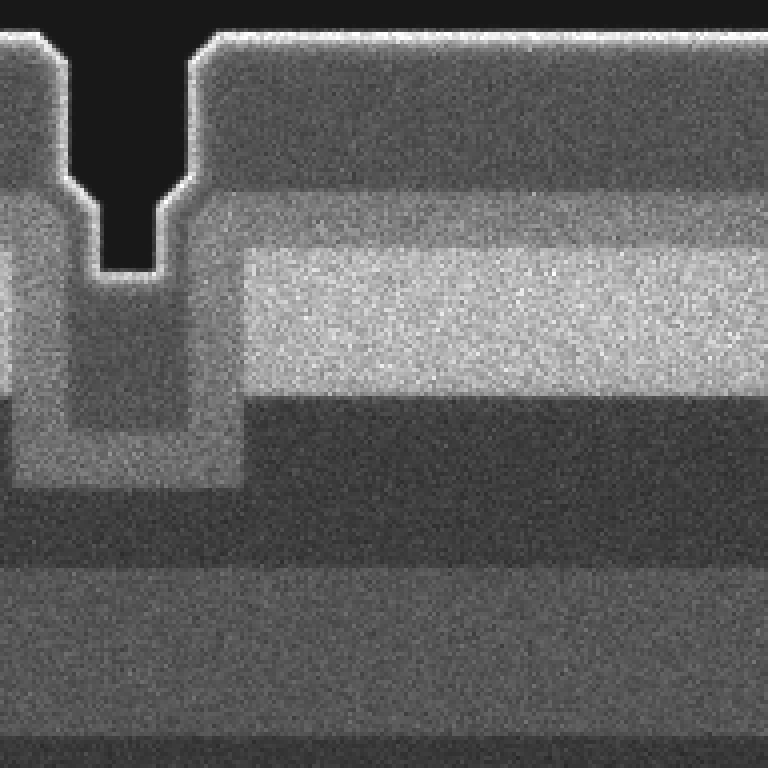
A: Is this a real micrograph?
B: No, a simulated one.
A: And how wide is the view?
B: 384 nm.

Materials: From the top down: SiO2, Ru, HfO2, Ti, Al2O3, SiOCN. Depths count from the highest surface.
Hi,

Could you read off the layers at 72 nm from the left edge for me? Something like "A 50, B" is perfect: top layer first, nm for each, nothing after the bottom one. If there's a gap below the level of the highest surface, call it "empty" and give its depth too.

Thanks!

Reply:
empty 120, SiO2 80, Ru 28, Ti 40, Al2O3 84, SiOCN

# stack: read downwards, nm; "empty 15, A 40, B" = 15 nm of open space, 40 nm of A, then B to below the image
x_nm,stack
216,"SiO2 80, Ru 28, HfO2 74, Ti 86, Al2O3 84, SiOCN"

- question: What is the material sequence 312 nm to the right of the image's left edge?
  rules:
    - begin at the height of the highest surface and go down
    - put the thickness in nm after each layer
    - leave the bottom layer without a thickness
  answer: SiO2 80, Ru 28, HfO2 74, Ti 86, Al2O3 84, SiOCN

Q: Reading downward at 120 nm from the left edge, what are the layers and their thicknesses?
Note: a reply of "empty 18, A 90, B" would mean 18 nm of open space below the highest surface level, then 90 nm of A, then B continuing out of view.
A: SiO2 80, Ru 148, Ti 40, Al2O3 84, SiOCN